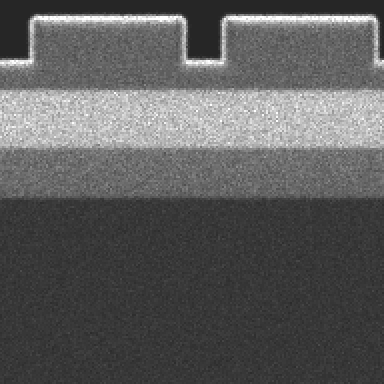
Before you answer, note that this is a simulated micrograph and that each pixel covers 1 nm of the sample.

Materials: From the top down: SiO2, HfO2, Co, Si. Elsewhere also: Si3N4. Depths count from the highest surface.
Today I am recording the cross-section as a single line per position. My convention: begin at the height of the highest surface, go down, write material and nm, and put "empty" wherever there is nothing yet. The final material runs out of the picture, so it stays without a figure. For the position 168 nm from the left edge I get SiO2 74, HfO2 58, Co 50, Si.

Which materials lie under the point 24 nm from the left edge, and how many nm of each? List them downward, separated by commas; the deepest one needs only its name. empty 44, SiO2 30, HfO2 58, Co 50, Si